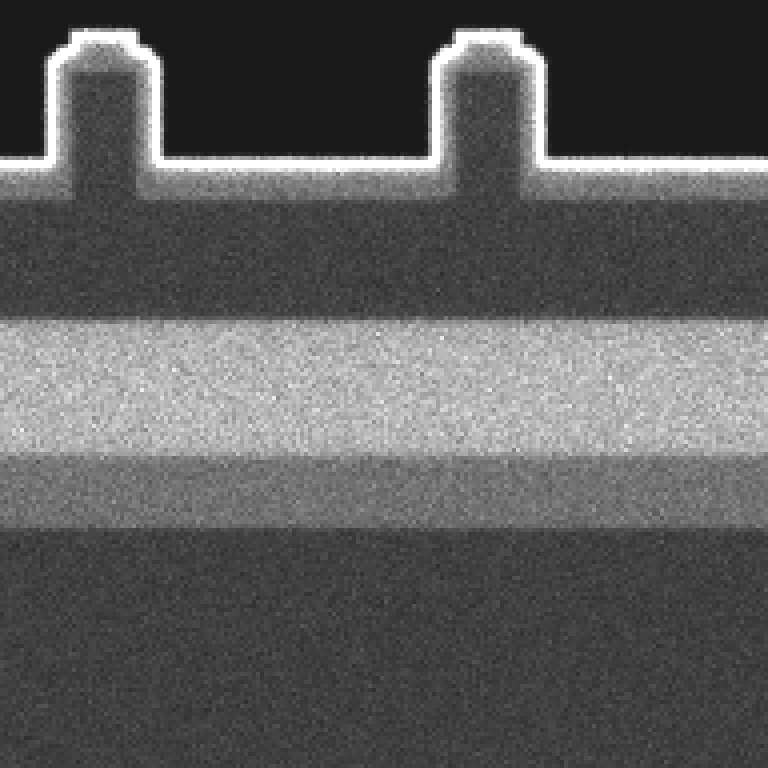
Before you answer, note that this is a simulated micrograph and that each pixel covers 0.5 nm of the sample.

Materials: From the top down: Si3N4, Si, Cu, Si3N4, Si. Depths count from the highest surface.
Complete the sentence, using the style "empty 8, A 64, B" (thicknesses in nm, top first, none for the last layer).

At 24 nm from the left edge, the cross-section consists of empty 14, Si3N4 70, Si 60, Cu 68, Si3N4 36, Si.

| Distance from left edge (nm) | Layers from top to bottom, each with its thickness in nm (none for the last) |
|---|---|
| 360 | empty 64, Si3N4 20, Si 60, Cu 68, Si3N4 36, Si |